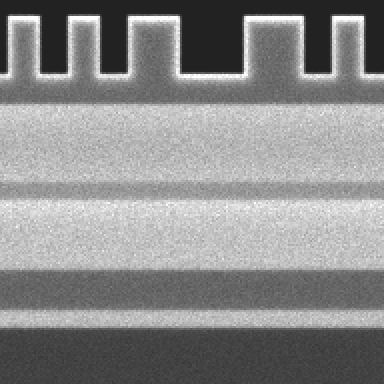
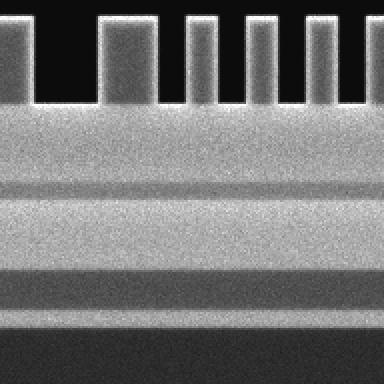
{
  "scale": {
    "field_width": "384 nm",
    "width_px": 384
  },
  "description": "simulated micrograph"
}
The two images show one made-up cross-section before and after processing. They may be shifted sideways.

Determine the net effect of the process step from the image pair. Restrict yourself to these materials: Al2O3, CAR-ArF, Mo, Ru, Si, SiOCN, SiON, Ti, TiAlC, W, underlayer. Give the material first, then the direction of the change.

underlayer: removed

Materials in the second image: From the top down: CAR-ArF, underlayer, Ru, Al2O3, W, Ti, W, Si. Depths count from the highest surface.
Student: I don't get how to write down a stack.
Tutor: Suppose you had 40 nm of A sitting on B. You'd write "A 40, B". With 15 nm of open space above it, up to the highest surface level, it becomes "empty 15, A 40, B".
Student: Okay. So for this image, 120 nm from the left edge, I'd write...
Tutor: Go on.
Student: CAR-ArF 58, underlayer 30, Ru 78, Al2O3 18, W 70, Ti 40, W 18, Si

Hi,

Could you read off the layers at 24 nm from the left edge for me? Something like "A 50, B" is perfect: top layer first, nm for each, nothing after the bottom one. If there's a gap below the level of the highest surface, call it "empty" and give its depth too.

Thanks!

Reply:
CAR-ArF 58, underlayer 30, Ru 78, Al2O3 18, W 70, Ti 40, W 18, Si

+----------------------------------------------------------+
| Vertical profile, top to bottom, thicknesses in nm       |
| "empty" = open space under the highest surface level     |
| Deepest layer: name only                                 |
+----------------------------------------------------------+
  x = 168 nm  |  empty 88, Ru 78, Al2O3 18, W 70, Ti 40, W 18, Si